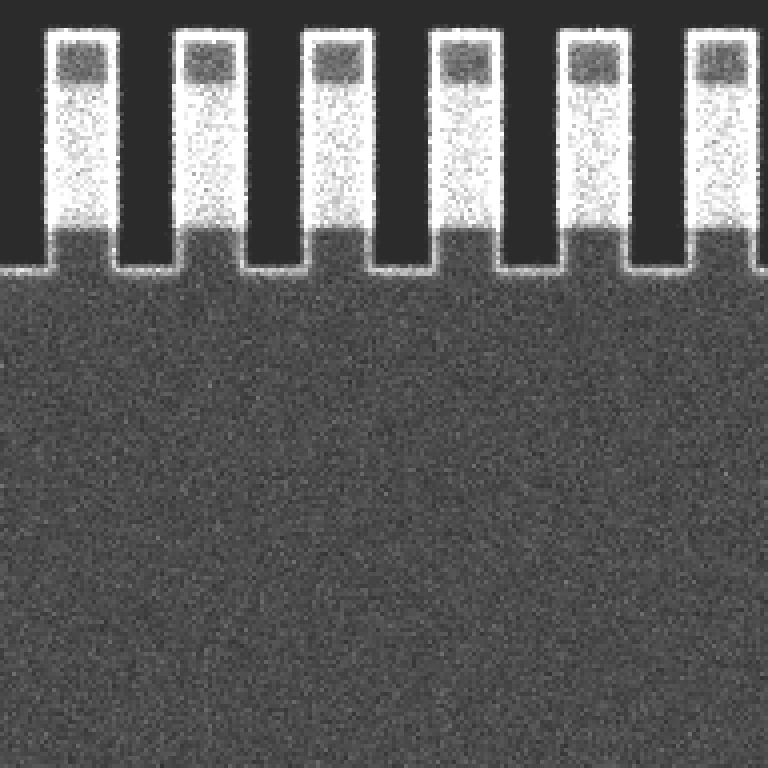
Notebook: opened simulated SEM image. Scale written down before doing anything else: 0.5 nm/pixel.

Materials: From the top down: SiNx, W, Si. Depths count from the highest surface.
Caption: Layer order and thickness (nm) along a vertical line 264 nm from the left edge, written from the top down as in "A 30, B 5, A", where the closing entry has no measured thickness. empty 118, Si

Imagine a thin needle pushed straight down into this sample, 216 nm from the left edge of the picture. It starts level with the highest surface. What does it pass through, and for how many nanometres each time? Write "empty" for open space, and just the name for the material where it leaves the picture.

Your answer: SiNx 26, W 72, Si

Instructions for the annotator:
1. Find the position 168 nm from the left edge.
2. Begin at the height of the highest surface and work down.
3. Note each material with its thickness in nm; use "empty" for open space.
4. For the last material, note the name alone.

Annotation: SiNx 26, W 72, Si